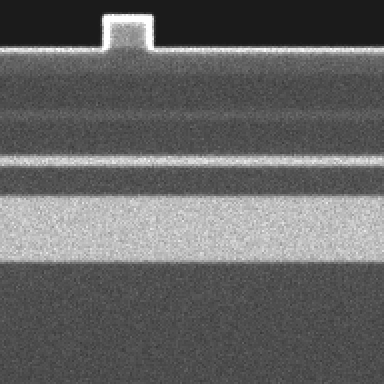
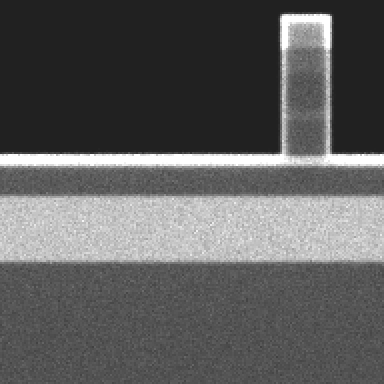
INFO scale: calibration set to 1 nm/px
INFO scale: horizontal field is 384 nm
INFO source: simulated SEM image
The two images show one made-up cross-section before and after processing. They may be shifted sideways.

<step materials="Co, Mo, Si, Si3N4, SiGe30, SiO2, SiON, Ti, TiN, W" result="removed Si and SiGe30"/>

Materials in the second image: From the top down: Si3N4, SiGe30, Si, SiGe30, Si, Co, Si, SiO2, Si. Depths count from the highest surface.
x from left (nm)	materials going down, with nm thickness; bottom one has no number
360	empty 140, Co 10, Si 30, SiO2 66, Si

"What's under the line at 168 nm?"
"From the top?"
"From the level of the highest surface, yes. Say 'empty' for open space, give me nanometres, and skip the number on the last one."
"empty 140, Co 10, Si 30, SiO2 66, Si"